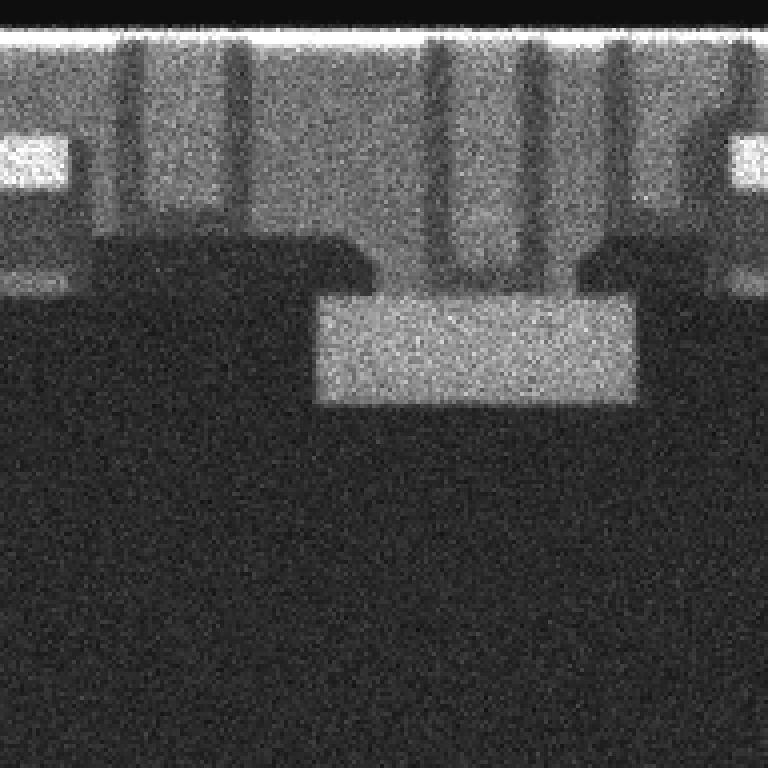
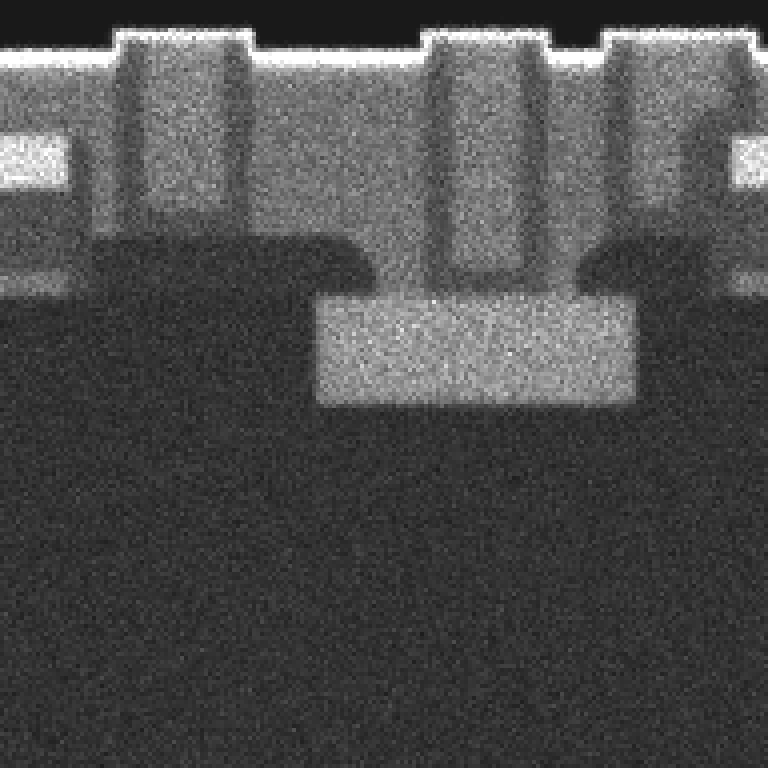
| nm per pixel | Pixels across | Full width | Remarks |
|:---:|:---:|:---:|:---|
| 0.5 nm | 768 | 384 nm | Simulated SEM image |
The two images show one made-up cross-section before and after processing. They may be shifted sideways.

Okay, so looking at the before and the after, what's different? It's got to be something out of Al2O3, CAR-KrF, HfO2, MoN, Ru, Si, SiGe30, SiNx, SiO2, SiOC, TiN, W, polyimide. SiO2, removed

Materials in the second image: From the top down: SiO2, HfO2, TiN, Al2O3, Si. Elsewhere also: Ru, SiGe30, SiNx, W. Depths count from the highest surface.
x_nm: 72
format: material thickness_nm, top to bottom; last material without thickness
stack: Ru 88, TiN 14, SiGe30 30, Si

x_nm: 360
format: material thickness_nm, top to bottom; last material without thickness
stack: Ru 38, TiN 14, SiNx 80, Si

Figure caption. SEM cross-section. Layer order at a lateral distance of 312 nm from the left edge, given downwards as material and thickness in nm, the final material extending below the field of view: TiN 102, SiGe30 30, W 54, Si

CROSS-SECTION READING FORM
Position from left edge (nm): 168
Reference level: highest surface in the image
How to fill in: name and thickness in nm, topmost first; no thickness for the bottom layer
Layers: empty 10, SiO2 92, SiGe30 30, W 54, Si